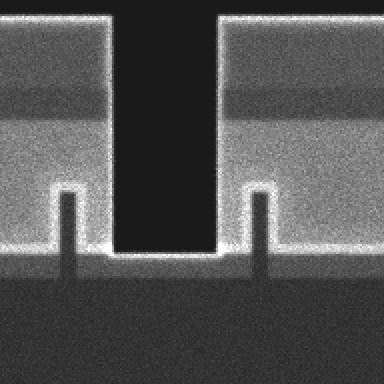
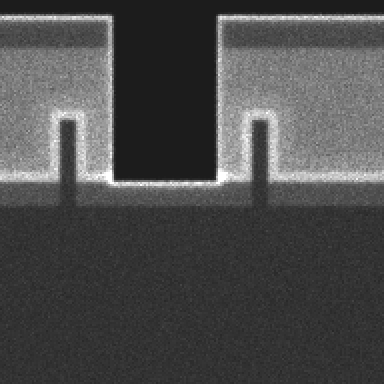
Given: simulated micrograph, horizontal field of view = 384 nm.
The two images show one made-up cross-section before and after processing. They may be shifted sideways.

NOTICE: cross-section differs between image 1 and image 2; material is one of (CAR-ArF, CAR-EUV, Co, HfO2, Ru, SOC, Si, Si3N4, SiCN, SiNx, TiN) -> removed: SOC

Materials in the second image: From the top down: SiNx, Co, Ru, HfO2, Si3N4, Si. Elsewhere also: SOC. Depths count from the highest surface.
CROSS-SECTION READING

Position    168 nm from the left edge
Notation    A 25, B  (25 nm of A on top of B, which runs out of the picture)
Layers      empty 166, Si3N4 24, Si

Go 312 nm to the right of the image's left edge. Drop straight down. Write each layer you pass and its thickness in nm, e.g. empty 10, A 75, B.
SiNx 32, Co 108, Ru 16, HfO2 10, Si3N4 24, Si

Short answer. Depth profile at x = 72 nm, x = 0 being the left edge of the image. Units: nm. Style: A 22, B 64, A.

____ SiNx 32, Co 46, Ru 16, HfO2 10, Si